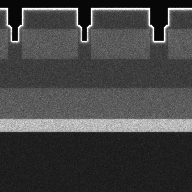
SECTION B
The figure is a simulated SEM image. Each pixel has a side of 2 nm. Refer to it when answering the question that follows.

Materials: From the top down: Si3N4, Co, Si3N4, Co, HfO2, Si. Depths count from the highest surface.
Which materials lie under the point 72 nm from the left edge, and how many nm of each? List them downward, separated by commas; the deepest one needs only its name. Si3N4 42, Co 60, Si3N4 58, Co 62, HfO2 26, Si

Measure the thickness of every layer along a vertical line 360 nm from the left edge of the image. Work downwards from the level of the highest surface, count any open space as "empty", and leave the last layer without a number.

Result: Si3N4 42, Co 60, Si3N4 58, Co 62, HfO2 26, Si